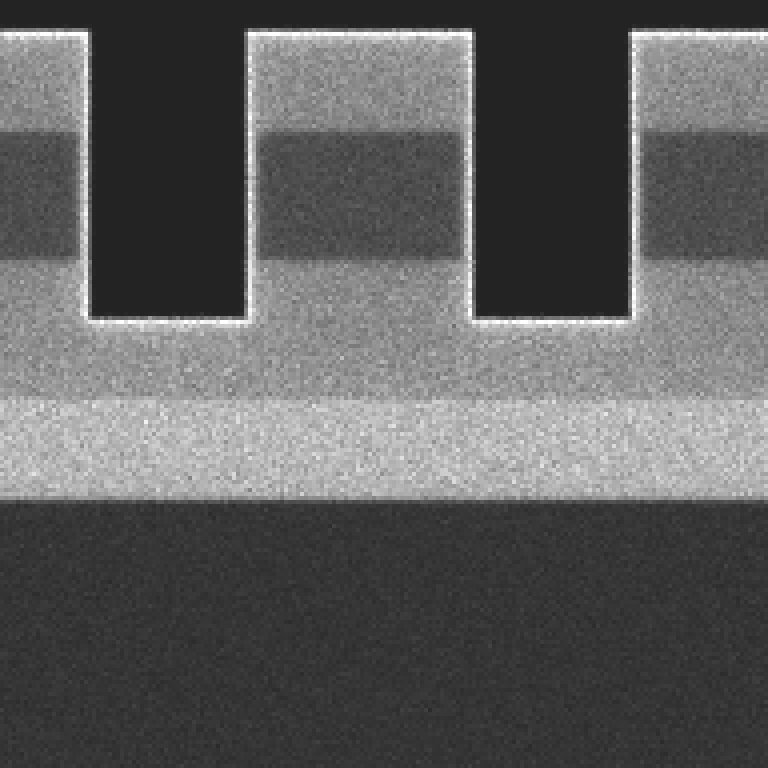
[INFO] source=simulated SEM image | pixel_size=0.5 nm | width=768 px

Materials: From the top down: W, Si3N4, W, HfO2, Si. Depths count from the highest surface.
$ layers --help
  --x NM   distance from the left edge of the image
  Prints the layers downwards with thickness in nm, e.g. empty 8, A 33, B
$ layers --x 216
W 50, Si3N4 64, W 70, HfO2 50, Si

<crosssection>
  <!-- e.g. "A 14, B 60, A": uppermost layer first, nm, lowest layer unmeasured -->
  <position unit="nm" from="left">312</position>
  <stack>empty 144, W 40, HfO2 50, Si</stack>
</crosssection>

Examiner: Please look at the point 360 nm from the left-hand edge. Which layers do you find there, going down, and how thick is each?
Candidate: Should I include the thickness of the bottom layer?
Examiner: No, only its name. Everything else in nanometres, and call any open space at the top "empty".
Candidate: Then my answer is W 50, Si3N4 64, W 70, HfO2 50, Si